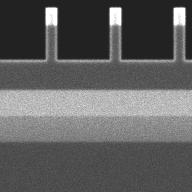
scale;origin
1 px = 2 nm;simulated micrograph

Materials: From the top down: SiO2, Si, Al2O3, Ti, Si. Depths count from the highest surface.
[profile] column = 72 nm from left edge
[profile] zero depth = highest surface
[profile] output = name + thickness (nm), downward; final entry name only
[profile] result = empty 104, Si 60, Al2O3 52, Ti 52, Si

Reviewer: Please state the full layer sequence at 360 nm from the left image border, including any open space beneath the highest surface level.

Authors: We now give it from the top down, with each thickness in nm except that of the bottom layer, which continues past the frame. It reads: SiO2 34, Si 130, Al2O3 52, Ti 52, Si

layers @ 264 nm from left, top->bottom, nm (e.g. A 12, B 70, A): empty 104, Si 60, Al2O3 52, Ti 52, Si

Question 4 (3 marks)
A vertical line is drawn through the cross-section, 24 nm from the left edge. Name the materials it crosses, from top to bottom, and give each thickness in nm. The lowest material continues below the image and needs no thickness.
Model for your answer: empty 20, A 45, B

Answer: empty 104, Si 60, Al2O3 52, Ti 52, Si